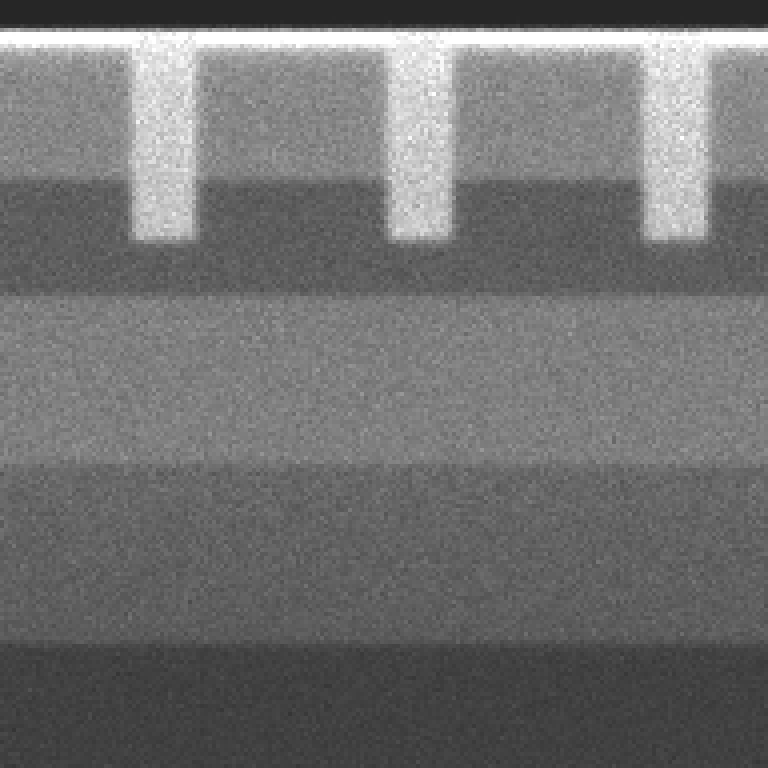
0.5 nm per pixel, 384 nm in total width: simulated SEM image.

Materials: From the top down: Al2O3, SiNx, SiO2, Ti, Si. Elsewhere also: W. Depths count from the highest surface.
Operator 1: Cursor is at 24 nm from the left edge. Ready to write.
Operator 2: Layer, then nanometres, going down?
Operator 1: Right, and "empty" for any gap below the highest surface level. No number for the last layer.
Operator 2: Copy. Al2O3 74, SiNx 58, SiO2 84, Ti 90, Si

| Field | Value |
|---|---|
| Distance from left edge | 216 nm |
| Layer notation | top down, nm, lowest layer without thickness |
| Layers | W 104, SiNx 28, SiO2 84, Ti 90, Si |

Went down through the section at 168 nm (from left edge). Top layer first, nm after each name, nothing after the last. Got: Al2O3 74, SiNx 58, SiO2 84, Ti 90, Si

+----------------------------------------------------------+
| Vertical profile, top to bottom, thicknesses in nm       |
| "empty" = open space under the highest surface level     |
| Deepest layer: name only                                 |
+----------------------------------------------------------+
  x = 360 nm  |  Al2O3 74, SiNx 58, SiO2 84, Ti 90, Si